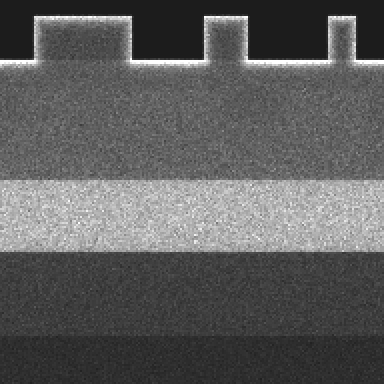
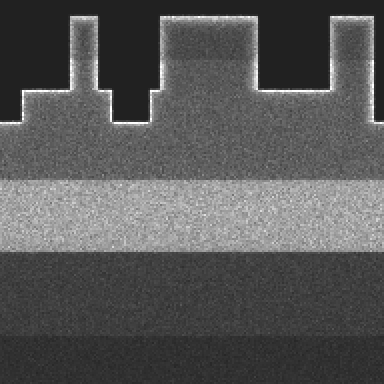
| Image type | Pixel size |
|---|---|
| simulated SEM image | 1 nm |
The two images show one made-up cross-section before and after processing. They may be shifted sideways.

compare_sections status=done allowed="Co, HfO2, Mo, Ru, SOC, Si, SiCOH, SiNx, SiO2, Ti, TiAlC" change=removed material="SiO2"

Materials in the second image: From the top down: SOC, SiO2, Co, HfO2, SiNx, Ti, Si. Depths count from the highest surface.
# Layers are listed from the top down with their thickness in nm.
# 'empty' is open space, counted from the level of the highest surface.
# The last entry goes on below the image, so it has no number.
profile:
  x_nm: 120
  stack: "empty 106, Co 58, HfO2 72, SiNx 26, Ti 58, Si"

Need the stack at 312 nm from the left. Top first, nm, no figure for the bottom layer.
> empty 74, Co 90, HfO2 72, SiNx 26, Ti 58, Si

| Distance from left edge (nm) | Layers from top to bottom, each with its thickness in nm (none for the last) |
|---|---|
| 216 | SOC 44, SiO2 30, Co 90, HfO2 72, SiNx 26, Ti 58, Si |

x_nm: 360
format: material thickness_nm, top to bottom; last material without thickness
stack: SOC 44, SiO2 62, Co 58, HfO2 72, SiNx 26, Ti 58, Si